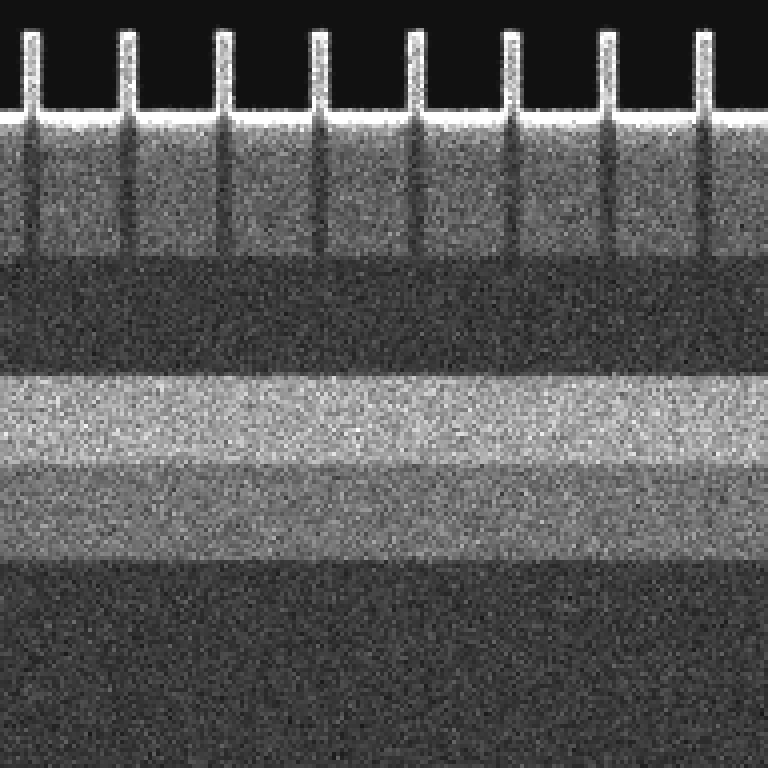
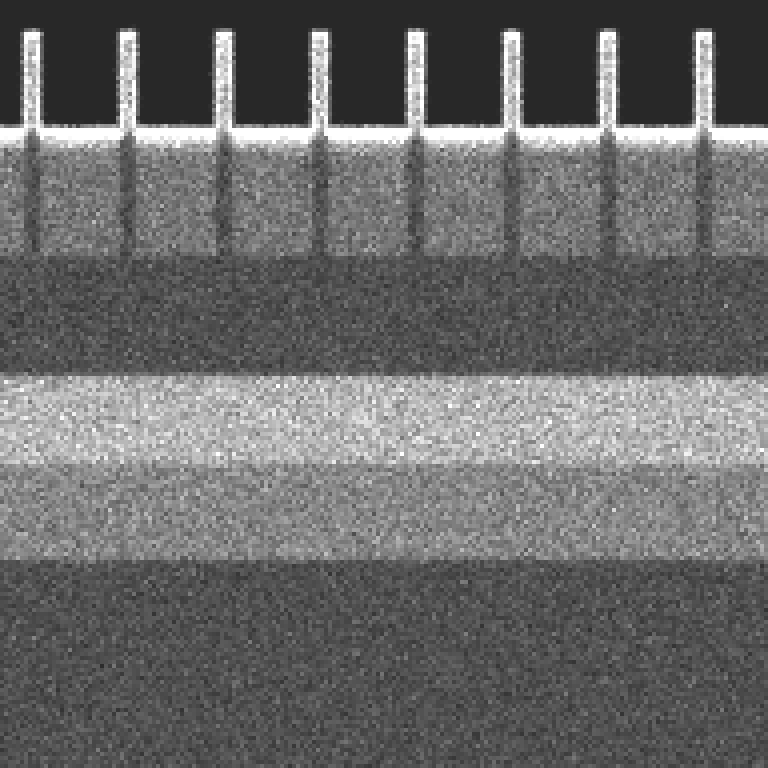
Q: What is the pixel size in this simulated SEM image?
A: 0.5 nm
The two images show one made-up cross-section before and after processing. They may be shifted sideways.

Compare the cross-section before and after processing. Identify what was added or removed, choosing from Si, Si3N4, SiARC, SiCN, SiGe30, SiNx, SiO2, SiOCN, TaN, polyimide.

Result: SiARC removed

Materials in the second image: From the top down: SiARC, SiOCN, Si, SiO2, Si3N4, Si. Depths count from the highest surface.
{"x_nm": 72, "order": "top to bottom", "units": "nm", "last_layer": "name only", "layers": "empty 48, SiARC 10, SiOCN 54, Si 60, SiO2 44, Si3N4 48, Si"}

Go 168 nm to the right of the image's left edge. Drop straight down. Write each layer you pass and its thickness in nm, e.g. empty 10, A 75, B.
empty 48, SiARC 10, SiOCN 54, Si 60, SiO2 44, Si3N4 48, Si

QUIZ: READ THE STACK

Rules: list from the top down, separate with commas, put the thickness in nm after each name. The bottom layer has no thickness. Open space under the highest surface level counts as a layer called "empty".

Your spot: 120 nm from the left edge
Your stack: empty 48, SiARC 10, SiOCN 54, Si 60, SiO2 44, Si3N4 48, Si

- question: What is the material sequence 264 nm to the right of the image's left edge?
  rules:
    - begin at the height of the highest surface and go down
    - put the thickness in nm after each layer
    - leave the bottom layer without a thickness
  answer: empty 48, SiARC 10, SiOCN 54, Si 60, SiO2 44, Si3N4 48, Si